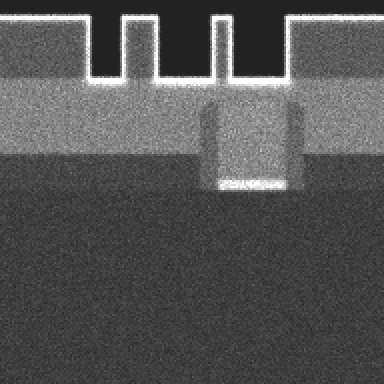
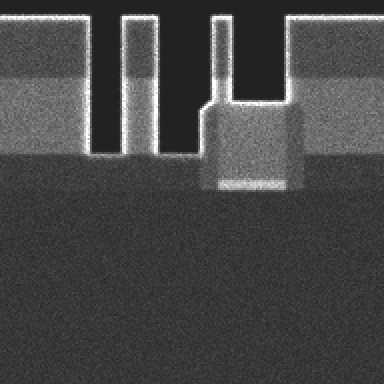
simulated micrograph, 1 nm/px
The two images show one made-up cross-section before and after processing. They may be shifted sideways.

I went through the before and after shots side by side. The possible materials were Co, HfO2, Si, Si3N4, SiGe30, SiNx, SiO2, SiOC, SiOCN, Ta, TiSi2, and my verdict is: removed, SiO2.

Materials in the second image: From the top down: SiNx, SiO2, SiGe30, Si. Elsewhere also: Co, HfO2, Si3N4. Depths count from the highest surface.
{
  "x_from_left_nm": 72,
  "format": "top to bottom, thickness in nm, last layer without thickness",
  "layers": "SiNx 62, SiO2 76, SiGe30 36, Si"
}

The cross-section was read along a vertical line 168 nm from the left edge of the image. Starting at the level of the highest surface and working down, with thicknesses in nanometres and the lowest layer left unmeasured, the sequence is empty 138, SiGe30 36, Si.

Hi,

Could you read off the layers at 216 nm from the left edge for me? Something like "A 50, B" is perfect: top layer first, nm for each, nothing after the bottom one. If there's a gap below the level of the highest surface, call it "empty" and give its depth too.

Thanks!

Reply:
SiNx 62, SiO2 24, Si3N4 88, Si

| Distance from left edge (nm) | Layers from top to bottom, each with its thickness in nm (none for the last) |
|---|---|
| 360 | SiNx 62, SiO2 76, SiGe30 36, Si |